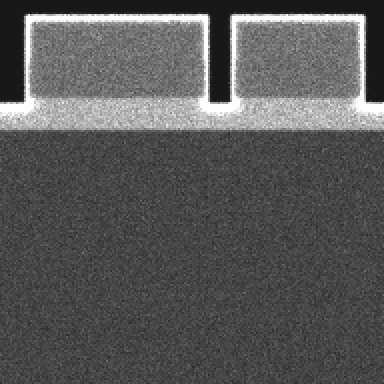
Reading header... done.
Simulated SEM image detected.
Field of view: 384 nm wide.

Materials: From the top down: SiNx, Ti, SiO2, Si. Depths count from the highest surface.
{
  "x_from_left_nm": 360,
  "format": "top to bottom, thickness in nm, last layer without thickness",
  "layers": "SiNx 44, Ti 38, SiO2 32, Si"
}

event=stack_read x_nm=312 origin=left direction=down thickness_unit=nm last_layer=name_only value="SiNx 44, Ti 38, SiO2 32, Si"